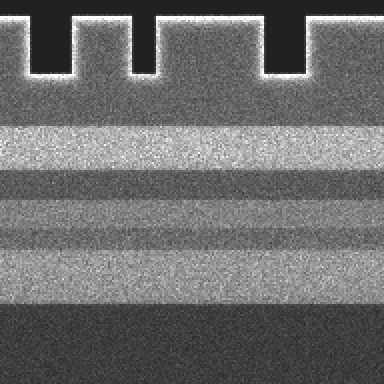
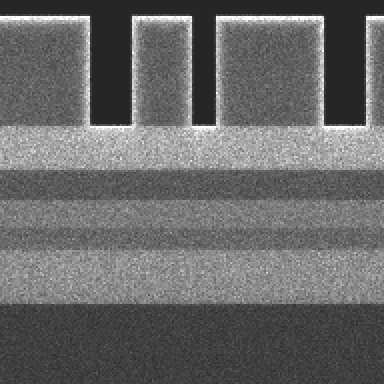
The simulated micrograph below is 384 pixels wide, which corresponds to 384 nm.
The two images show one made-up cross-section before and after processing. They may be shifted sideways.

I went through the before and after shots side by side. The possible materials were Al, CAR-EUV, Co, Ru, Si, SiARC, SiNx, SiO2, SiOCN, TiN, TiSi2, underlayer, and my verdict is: removed, underlayer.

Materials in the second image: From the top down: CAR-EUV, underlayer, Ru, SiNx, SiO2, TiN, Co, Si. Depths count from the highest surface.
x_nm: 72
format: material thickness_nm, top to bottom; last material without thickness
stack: CAR-EUV 58, underlayer 52, Ru 44, SiNx 30, SiO2 28, TiN 22, Co 54, Si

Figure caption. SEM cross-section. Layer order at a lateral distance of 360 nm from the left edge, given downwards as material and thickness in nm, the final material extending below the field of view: empty 110, Ru 44, SiNx 30, SiO2 28, TiN 22, Co 54, Si